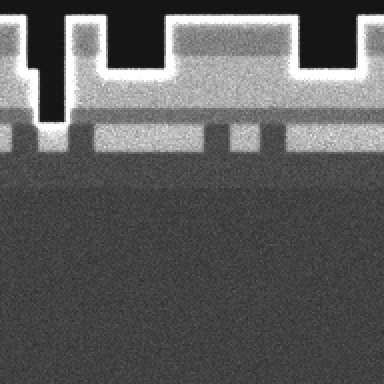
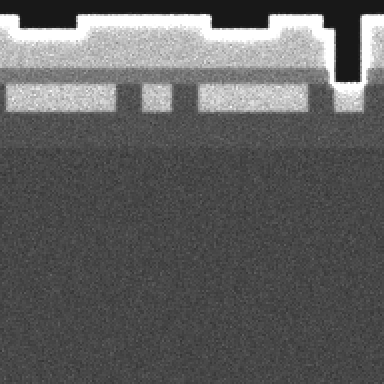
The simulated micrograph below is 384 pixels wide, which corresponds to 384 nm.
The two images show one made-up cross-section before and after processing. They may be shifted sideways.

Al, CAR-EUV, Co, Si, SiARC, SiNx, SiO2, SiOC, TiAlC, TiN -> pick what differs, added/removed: SiARC removed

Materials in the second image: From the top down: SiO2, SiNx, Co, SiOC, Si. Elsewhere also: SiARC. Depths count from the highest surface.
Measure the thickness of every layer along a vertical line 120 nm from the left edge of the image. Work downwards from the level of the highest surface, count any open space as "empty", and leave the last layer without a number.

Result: SiO2 52, SiNx 16, SiOC 64, Si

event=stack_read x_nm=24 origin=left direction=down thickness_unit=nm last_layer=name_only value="empty 14, SiO2 38, SiNx 16, Co 28, SiOC 36, Si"